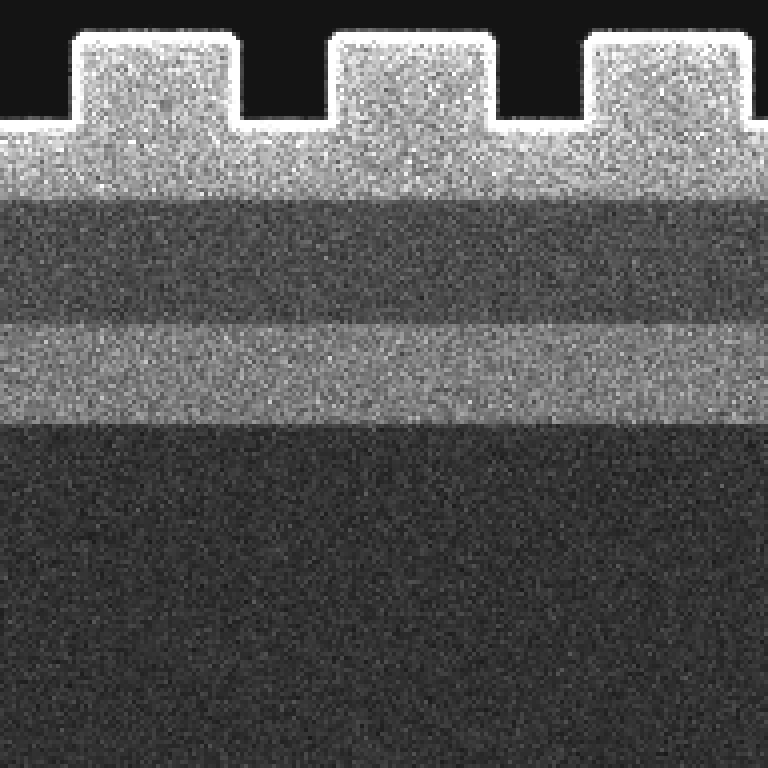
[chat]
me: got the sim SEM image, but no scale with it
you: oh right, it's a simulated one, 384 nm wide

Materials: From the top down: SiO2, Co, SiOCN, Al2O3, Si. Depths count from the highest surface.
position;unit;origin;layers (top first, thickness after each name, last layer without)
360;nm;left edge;SiO2 10, Co 74, SiOCN 62, Al2O3 50, Si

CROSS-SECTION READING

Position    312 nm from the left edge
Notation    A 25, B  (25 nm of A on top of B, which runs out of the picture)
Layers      SiO2 10, Co 74, SiOCN 62, Al2O3 50, Si